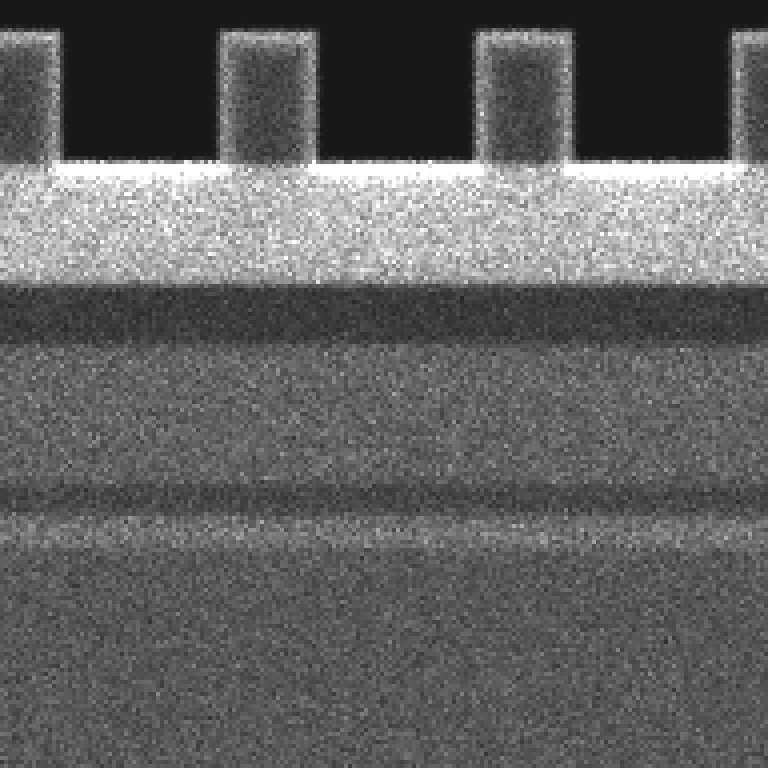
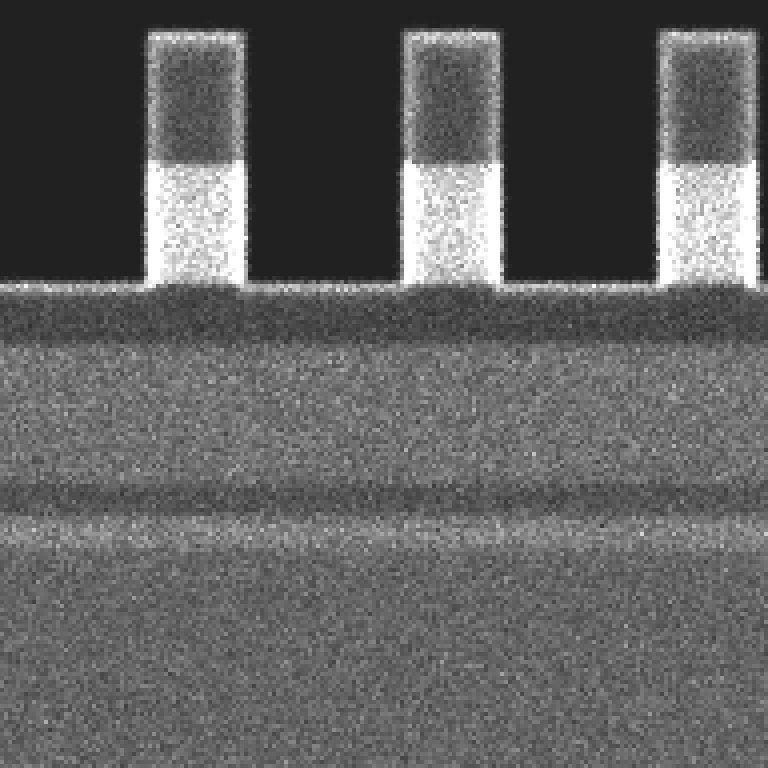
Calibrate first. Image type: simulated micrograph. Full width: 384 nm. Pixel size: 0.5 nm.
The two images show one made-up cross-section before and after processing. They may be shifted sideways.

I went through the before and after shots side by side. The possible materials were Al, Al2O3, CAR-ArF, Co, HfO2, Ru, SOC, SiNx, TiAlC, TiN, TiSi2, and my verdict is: removed, HfO2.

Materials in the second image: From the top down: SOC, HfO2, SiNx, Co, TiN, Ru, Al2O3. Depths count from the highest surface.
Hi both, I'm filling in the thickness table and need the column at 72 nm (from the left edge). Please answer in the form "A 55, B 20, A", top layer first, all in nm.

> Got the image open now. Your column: empty 126, SiNx 30, Co 70, TiN 16, Ru 16, Al2O3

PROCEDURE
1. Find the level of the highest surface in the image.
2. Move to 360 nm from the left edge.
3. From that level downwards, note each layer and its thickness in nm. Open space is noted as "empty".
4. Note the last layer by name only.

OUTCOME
SOC 66, HfO2 60, SiNx 30, Co 70, TiN 16, Ru 16, Al2O3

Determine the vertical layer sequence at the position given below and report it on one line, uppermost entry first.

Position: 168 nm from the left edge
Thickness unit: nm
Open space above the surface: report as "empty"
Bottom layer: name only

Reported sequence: empty 126, SiNx 30, Co 70, TiN 16, Ru 16, Al2O3